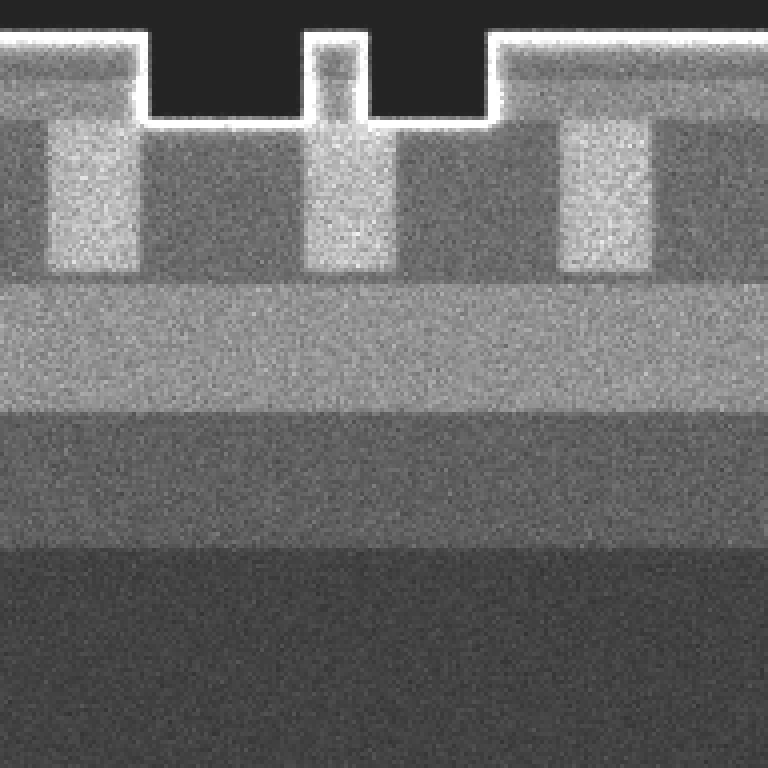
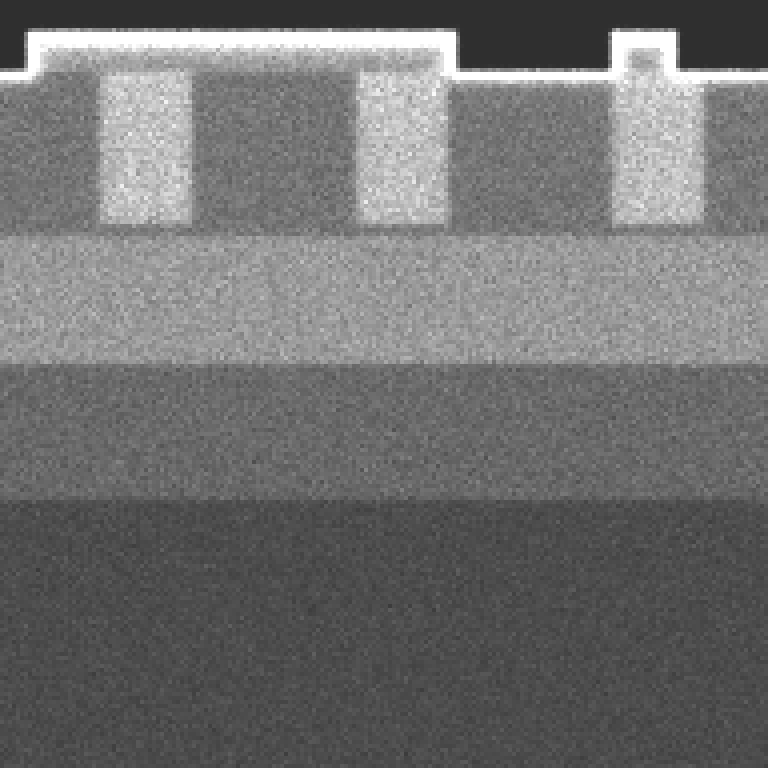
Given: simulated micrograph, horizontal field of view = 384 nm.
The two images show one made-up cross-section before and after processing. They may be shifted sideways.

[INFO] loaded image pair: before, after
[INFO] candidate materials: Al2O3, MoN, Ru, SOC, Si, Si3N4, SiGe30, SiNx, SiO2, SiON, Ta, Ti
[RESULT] removed SOC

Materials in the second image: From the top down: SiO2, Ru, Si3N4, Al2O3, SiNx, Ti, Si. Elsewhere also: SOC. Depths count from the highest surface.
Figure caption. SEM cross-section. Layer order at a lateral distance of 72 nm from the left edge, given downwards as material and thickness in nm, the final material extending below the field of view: SiO2 20, Ru 76, Si3N4 6, Al2O3 64, SiNx 40, Ti 28, Si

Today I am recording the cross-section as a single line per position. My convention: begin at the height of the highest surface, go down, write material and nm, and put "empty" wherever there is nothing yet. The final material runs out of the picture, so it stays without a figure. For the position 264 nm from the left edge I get empty 20, Si3N4 82, Al2O3 64, SiNx 40, Ti 28, Si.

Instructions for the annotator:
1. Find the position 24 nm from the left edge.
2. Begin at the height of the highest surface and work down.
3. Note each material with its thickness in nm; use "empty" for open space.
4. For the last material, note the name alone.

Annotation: SiO2 20, Si3N4 82, Al2O3 64, SiNx 40, Ti 28, Si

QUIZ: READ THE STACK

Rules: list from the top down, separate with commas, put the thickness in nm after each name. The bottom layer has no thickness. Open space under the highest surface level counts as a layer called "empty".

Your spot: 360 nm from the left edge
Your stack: empty 20, Si3N4 82, Al2O3 64, SiNx 40, Ti 28, Si